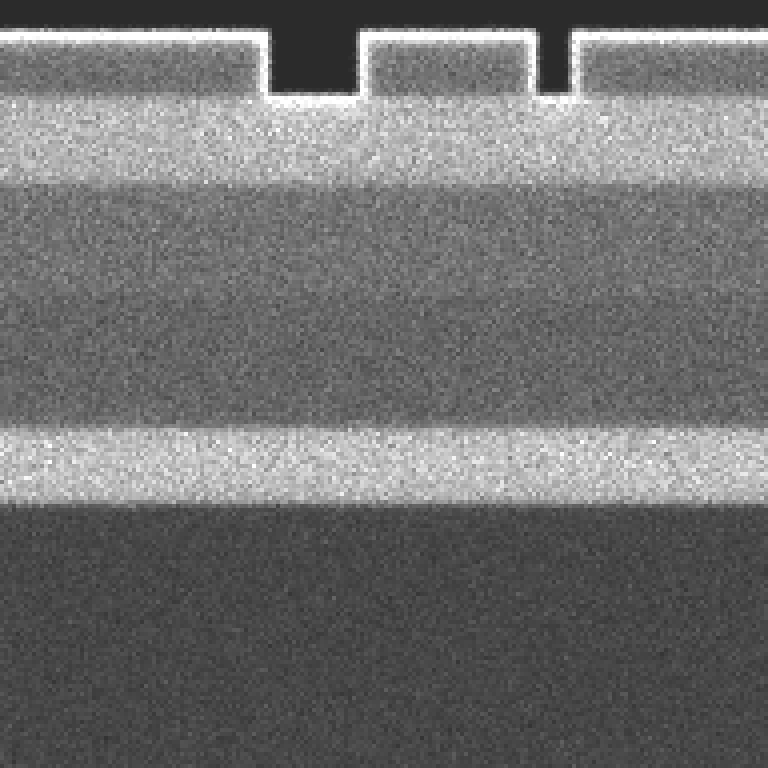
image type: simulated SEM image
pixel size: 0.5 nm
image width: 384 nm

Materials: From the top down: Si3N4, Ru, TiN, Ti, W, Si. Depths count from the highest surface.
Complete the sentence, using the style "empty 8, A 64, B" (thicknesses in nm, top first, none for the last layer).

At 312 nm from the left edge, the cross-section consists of Si3N4 32, Ru 44, TiN 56, Ti 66, W 38, Si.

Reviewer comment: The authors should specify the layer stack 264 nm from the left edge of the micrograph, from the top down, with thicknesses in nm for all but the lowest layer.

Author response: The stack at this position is Si3N4 32, Ru 44, TiN 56, Ti 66, W 38, Si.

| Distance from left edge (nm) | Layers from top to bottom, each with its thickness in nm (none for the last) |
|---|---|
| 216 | Si3N4 32, Ru 44, TiN 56, Ti 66, W 38, Si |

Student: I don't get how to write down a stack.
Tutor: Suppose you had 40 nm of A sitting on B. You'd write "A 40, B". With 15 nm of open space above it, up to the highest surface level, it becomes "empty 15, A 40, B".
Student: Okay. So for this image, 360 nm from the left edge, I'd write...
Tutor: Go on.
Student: Si3N4 32, Ru 44, TiN 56, Ti 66, W 38, Si